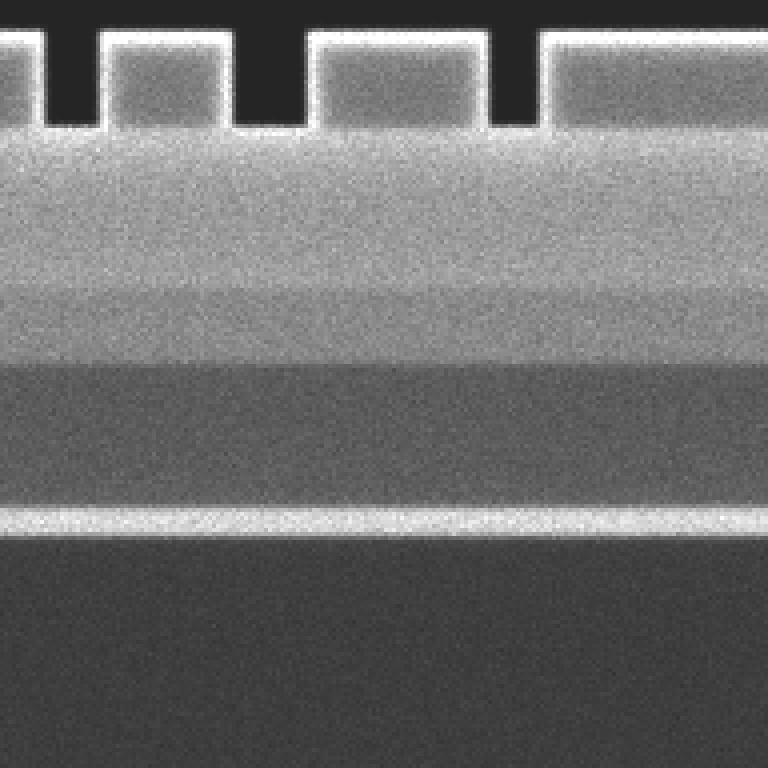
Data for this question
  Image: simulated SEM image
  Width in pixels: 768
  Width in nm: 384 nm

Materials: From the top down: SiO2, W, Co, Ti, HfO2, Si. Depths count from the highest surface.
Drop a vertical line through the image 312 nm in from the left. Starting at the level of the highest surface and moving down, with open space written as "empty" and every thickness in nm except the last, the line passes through SiO2 48, W 80, Co 38, Ti 72, HfO2 14, Si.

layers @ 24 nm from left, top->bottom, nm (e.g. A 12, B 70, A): empty 48, W 80, Co 38, Ti 72, HfO2 14, Si